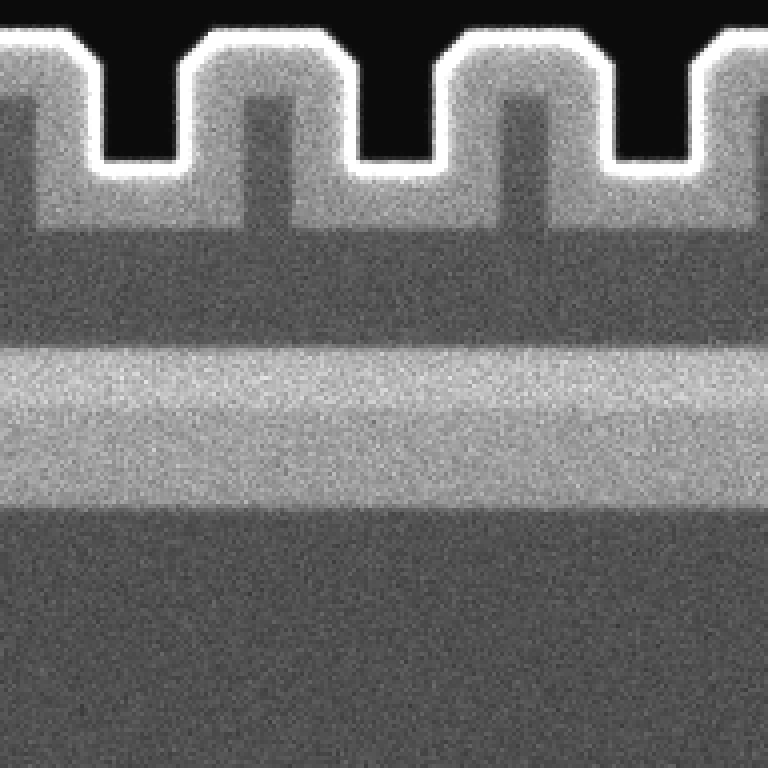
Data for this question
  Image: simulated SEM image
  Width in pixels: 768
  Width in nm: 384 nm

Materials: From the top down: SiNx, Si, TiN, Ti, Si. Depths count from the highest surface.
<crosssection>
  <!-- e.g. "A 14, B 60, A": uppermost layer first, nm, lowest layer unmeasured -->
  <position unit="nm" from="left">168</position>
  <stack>empty 8, SiNx 90, Si 60, TiN 30, Ti 50, Si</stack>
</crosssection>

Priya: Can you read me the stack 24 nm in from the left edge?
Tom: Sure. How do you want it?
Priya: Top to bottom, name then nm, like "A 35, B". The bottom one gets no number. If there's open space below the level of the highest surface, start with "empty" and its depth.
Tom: SiNx 98, Si 60, TiN 30, Ti 50, Si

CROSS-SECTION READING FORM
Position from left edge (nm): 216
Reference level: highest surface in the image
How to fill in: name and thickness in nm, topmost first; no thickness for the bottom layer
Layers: empty 66, SiNx 32, Si 60, TiN 30, Ti 50, Si